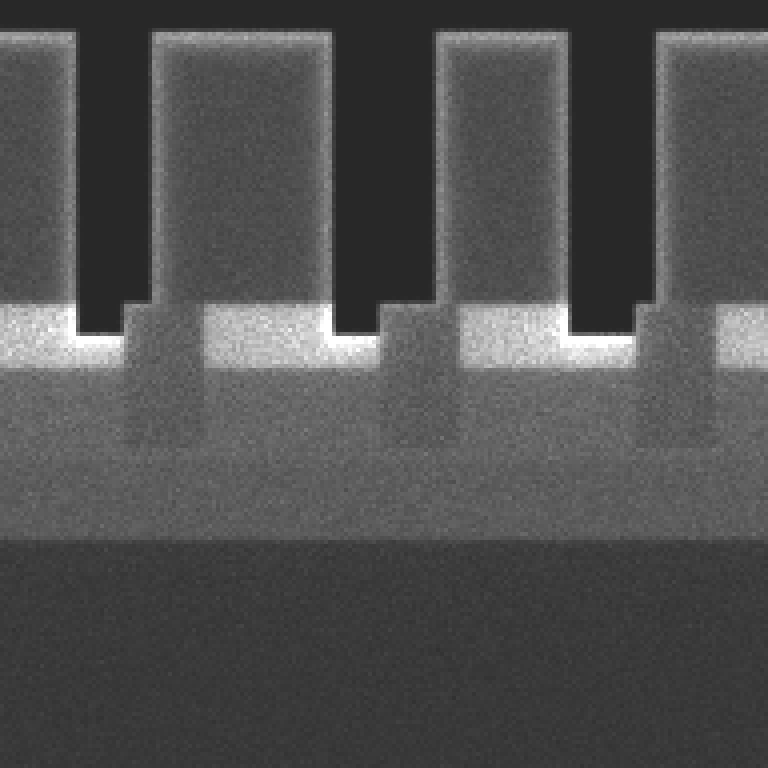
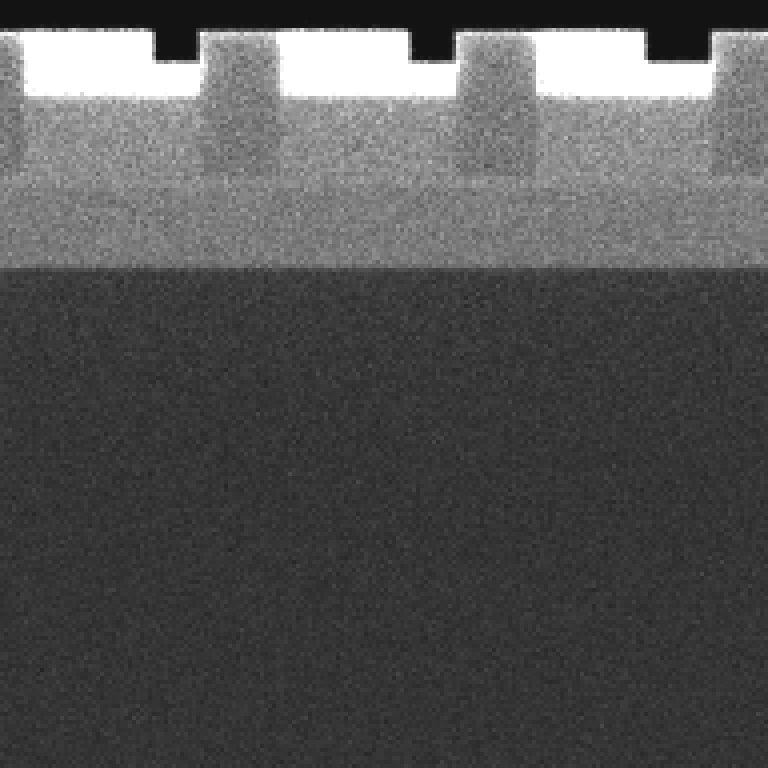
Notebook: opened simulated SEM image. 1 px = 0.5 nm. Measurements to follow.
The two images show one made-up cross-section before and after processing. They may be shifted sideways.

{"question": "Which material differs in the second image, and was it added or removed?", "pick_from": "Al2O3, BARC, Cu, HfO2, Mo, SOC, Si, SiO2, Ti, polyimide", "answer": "SOC, removed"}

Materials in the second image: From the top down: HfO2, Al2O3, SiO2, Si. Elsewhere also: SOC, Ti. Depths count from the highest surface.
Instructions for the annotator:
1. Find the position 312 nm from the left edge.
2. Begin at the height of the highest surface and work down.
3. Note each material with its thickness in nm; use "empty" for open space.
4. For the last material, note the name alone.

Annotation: HfO2 32, Al2O3 46, SiO2 40, Si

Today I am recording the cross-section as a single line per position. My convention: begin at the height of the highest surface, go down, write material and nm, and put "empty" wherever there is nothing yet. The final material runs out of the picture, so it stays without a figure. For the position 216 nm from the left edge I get empty 16, HfO2 16, Al2O3 46, SiO2 40, Si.